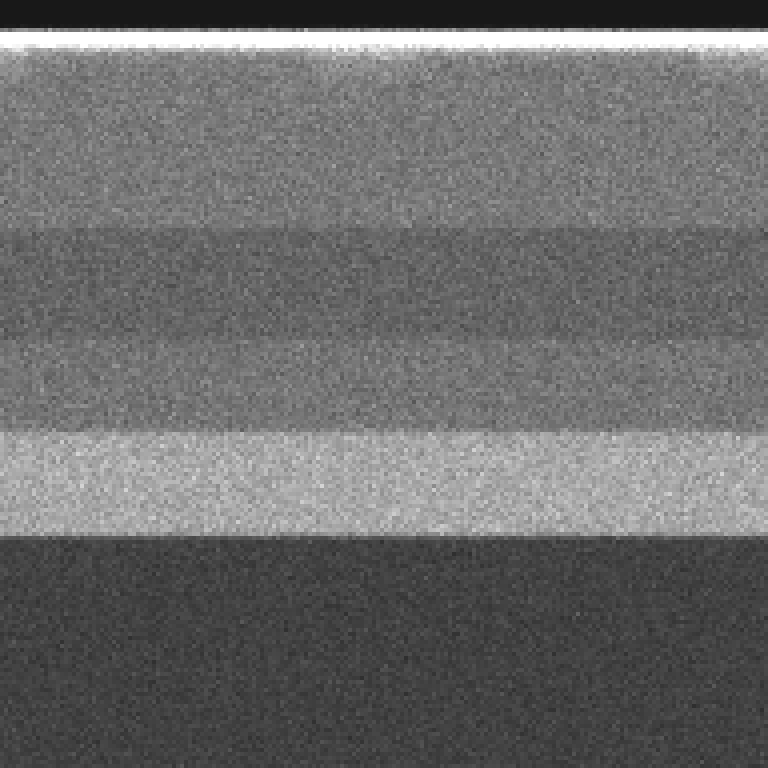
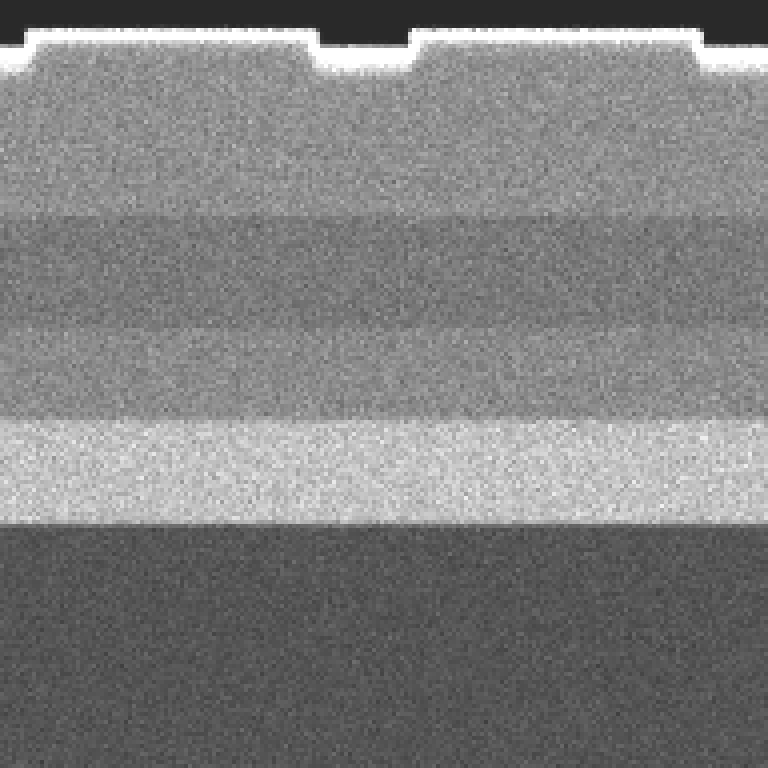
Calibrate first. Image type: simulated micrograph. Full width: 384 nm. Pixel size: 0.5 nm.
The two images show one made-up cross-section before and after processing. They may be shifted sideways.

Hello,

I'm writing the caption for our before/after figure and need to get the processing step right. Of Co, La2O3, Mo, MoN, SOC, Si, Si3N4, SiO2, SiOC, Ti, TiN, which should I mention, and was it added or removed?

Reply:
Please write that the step removed SOC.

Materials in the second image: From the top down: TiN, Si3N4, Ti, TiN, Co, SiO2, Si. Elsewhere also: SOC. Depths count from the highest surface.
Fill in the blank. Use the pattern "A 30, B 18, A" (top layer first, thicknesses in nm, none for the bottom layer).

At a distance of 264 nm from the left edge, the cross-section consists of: TiN 18, Si3N4 74, Ti 56, TiN 46, Co 14, SiO2 38, Si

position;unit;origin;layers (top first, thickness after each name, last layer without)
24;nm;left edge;TiN 18, Si3N4 74, Ti 56, TiN 46, Co 14, SiO2 38, Si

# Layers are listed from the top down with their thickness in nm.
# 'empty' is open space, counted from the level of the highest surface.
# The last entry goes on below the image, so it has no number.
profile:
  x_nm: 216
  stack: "TiN 18, Si3N4 74, Ti 56, TiN 46, Co 14, SiO2 38, Si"